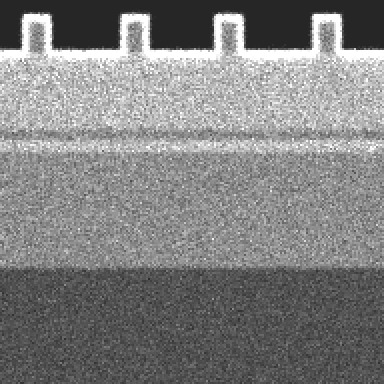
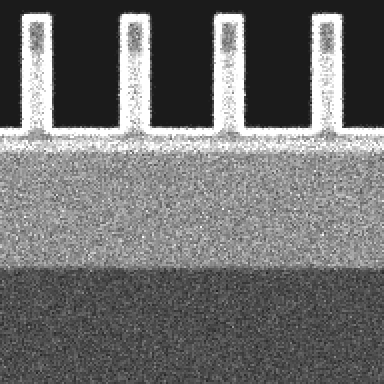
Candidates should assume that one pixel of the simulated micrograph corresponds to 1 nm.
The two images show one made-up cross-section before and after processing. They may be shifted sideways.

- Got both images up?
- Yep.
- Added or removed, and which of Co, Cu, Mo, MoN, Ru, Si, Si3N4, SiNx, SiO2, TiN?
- removed, Co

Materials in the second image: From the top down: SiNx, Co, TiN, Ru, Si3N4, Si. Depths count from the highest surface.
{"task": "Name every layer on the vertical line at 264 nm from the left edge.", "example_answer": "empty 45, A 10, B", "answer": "empty 114, TiN 10, Ru 12, Si3N4 116, Si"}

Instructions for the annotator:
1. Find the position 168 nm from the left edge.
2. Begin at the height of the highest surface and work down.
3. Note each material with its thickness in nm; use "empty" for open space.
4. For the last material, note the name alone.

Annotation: empty 114, TiN 10, Ru 12, Si3N4 116, Si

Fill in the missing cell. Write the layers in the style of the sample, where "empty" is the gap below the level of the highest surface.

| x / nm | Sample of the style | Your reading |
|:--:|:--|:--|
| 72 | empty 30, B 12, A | empty 114, TiN 10, Ru 12, Si3N4 116, Si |